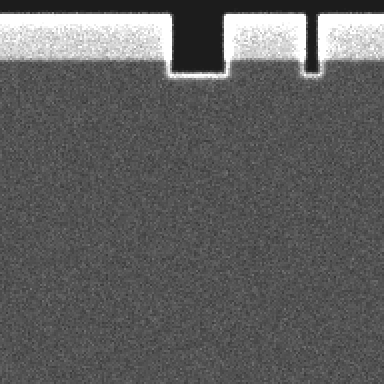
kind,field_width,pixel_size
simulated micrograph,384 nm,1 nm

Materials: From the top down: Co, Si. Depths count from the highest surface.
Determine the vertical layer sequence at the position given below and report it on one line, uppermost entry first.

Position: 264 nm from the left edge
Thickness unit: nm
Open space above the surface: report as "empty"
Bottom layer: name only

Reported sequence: Co 44, Si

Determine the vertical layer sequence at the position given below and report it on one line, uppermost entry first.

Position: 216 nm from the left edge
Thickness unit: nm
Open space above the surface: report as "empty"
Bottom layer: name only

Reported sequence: empty 58, Si